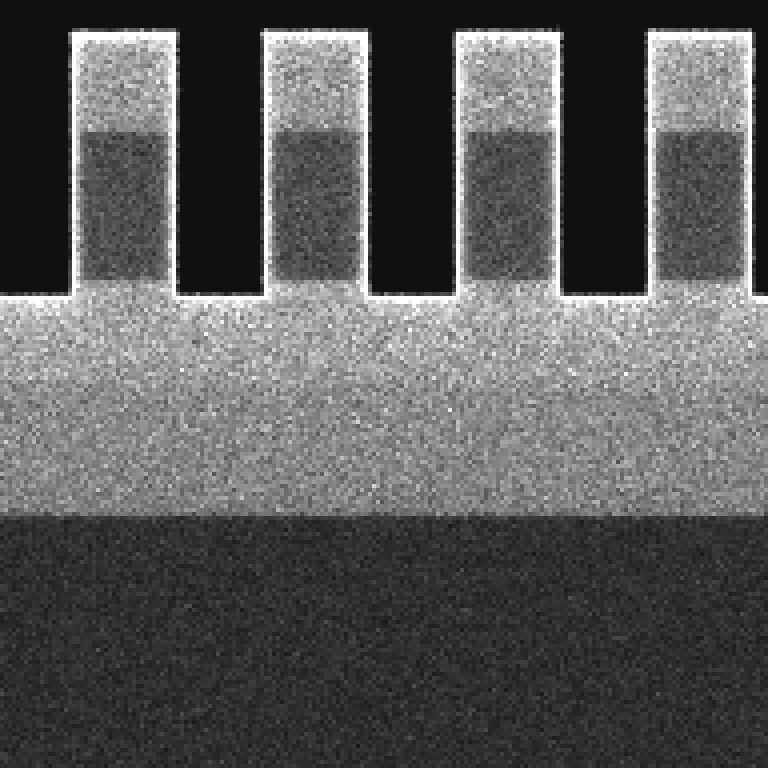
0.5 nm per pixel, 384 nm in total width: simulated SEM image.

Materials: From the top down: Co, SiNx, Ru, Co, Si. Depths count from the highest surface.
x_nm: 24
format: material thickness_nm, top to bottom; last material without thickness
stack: empty 132, Ru 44, Co 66, Si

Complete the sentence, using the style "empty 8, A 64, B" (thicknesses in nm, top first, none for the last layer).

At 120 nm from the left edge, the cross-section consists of empty 132, Ru 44, Co 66, Si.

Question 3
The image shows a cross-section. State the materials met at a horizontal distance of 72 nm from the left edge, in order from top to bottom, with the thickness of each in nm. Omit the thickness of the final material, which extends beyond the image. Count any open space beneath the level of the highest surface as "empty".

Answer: Co 50, SiNx 74, Ru 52, Co 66, Si